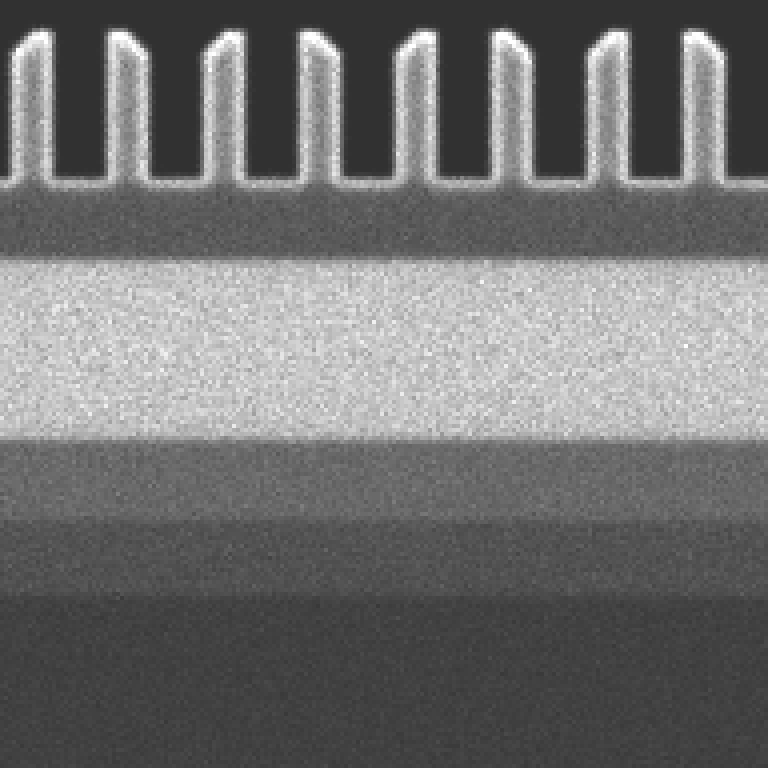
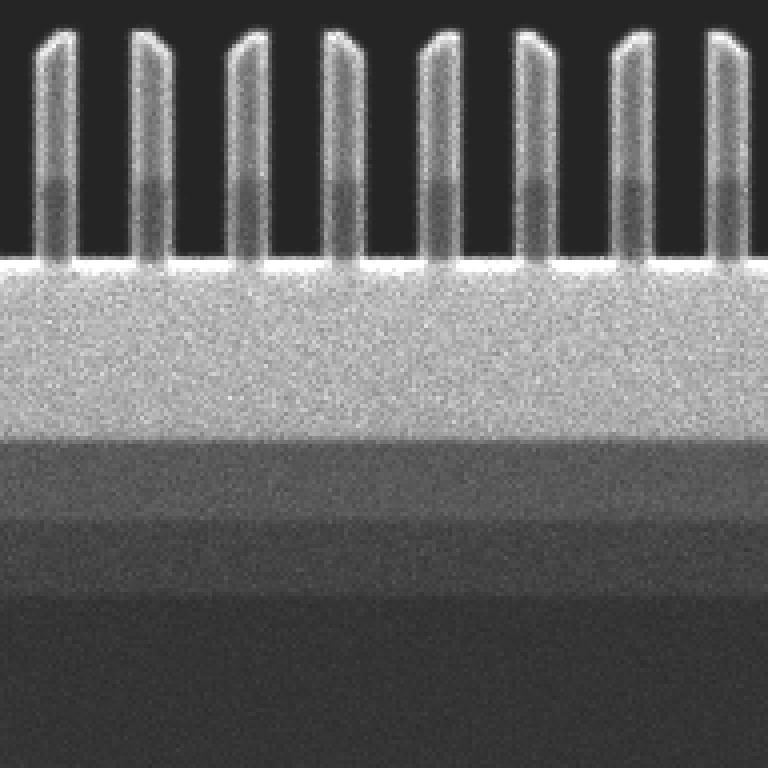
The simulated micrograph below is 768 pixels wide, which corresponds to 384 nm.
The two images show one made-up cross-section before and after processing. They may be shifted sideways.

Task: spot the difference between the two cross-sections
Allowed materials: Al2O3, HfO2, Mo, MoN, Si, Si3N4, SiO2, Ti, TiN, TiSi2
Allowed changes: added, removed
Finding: removed Si3N4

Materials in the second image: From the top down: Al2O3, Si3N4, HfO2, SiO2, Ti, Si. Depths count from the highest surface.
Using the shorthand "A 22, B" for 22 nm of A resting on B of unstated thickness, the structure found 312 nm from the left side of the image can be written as empty 4, Al2O3 70, Si3N4 40, HfO2 90, SiO2 40, Ti 38, Si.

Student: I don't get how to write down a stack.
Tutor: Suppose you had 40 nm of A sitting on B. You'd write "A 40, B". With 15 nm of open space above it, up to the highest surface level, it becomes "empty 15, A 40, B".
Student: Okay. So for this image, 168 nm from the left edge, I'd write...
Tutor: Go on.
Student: Al2O3 74, Si3N4 40, HfO2 90, SiO2 40, Ti 38, Si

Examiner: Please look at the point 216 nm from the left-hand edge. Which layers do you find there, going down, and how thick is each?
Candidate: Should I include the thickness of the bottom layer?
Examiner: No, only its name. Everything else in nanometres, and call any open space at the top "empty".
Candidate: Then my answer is empty 4, Al2O3 70, Si3N4 40, HfO2 90, SiO2 40, Ti 38, Si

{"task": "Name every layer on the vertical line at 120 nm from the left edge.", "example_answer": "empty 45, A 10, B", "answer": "empty 4, Al2O3 70, Si3N4 40, HfO2 90, SiO2 40, Ti 38, Si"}